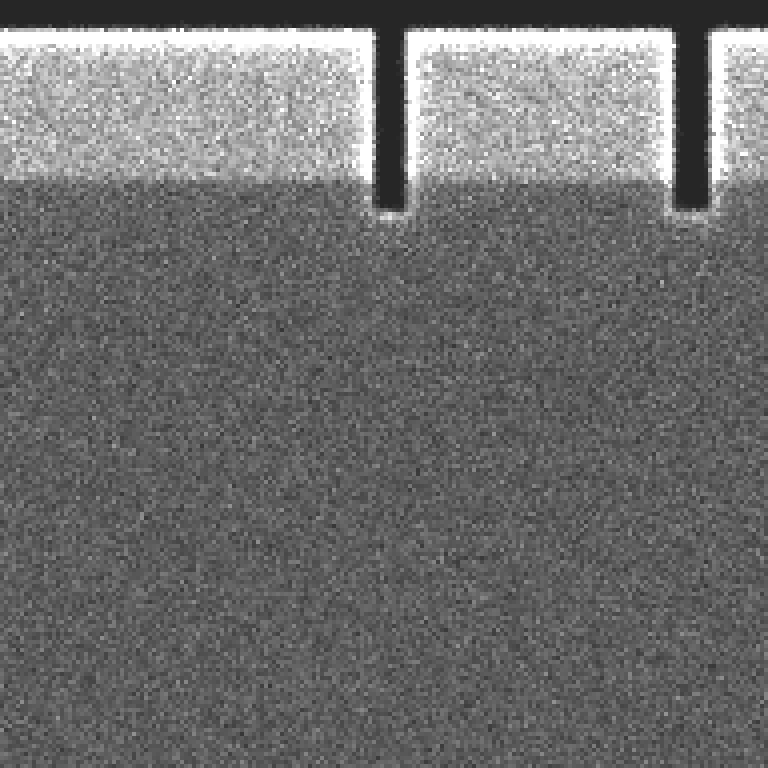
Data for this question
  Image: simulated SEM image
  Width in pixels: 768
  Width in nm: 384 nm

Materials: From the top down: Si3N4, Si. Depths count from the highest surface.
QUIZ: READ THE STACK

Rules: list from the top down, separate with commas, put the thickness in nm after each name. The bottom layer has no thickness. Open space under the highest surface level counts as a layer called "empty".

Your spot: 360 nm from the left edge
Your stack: Si3N4 74, Si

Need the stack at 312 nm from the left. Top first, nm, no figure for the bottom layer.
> Si3N4 74, Si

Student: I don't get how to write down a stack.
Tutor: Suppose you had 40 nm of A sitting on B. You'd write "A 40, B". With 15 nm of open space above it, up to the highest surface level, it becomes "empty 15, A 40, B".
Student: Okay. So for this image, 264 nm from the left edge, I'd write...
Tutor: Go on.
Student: Si3N4 74, Si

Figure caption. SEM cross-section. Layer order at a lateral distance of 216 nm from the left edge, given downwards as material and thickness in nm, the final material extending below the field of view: Si3N4 74, Si